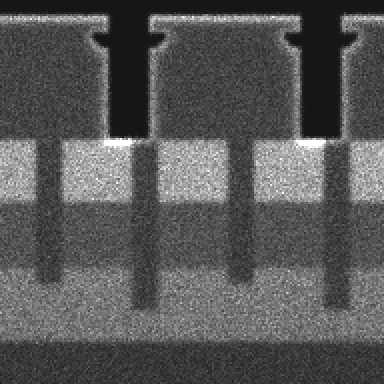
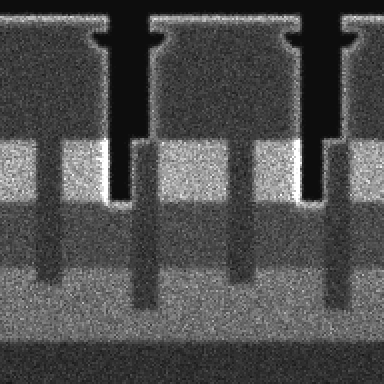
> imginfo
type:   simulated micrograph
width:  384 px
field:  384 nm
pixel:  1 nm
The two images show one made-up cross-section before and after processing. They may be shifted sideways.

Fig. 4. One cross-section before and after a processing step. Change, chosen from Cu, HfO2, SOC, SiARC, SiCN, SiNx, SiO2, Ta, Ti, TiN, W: HfO2 removed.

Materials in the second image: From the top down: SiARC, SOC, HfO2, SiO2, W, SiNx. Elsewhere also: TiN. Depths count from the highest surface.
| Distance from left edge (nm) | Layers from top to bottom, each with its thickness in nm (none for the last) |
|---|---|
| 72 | SiARC 16, SOC 108, HfO2 62, SiO2 66, W 74, SiNx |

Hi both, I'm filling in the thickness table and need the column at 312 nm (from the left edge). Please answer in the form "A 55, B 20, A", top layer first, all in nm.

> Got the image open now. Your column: empty 186, SiO2 66, W 74, SiNx